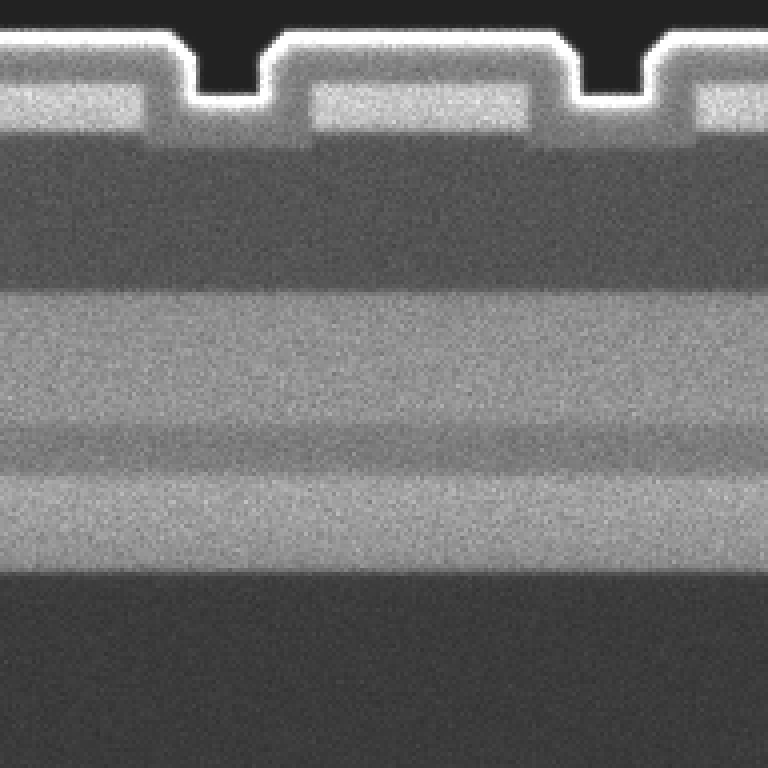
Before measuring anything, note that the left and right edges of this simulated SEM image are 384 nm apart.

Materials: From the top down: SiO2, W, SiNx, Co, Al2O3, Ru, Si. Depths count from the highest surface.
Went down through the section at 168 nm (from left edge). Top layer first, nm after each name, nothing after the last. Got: SiO2 26, W 24, SiNx 80, Co 66, Al2O3 26, Ru 48, Si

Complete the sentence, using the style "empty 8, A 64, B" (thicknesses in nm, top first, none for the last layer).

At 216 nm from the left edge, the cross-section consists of SiO2 26, W 24, SiNx 80, Co 66, Al2O3 26, Ru 48, Si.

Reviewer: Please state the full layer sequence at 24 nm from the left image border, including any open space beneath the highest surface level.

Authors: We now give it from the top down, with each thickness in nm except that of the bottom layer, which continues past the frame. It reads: SiO2 26, W 24, SiNx 80, Co 66, Al2O3 26, Ru 48, Si